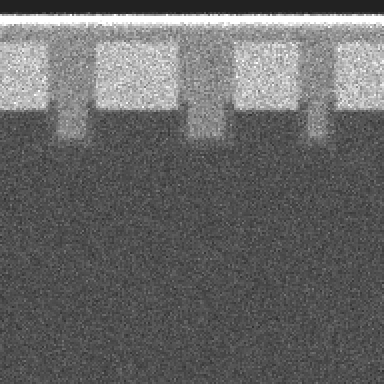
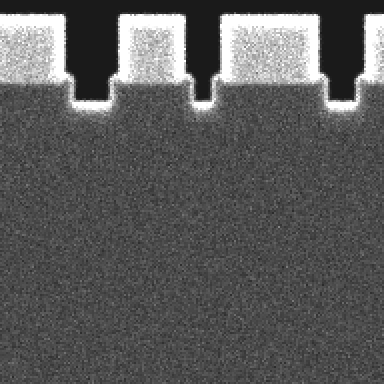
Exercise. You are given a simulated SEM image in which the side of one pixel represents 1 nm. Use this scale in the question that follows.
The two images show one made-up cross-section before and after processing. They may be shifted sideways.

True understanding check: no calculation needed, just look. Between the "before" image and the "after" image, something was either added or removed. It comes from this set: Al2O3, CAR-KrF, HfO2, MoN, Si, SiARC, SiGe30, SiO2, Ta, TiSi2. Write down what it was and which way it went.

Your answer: SiARC (removed)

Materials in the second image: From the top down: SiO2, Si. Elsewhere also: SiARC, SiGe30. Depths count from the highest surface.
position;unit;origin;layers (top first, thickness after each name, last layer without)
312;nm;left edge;SiO2 68, Si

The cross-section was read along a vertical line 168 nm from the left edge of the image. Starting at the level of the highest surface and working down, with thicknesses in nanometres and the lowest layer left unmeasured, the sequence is SiO2 68, Si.